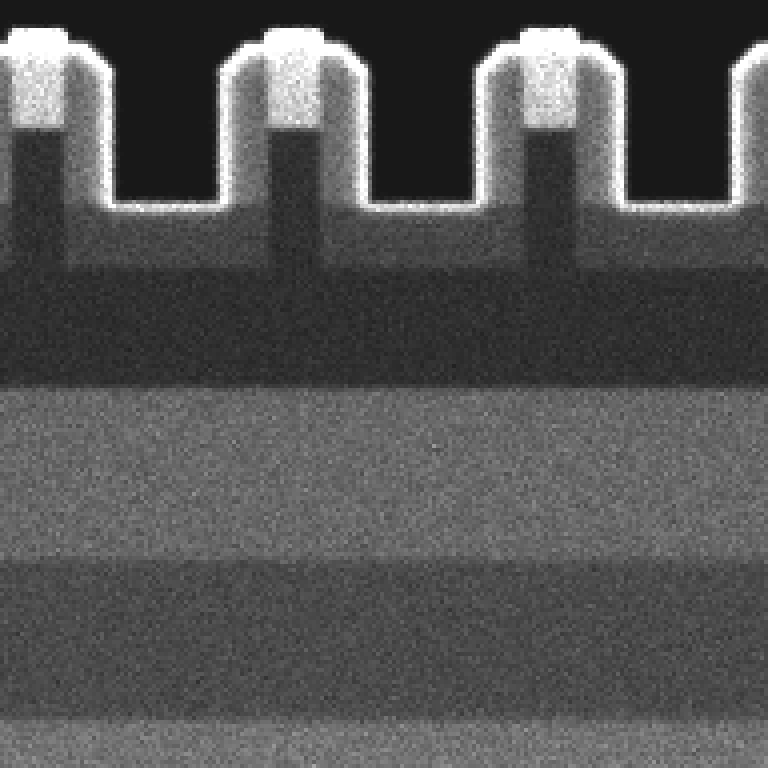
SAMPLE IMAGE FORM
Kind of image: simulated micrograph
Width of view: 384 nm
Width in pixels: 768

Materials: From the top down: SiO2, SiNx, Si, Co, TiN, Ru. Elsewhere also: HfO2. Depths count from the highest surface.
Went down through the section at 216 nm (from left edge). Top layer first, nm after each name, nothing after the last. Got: empty 86, SiNx 32, Si 60, Co 86, TiN 80, Ru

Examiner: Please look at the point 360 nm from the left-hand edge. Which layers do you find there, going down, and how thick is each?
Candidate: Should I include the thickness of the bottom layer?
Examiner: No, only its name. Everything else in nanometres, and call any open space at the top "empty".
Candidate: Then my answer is empty 86, SiNx 32, Si 60, Co 86, TiN 80, Ru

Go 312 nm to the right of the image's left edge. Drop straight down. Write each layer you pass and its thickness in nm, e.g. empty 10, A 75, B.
empty 86, SiNx 32, Si 60, Co 86, TiN 80, Ru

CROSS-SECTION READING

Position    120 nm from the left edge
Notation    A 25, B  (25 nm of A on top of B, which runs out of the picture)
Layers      empty 8, SiO2 78, SiNx 32, Si 60, Co 86, TiN 80, Ru